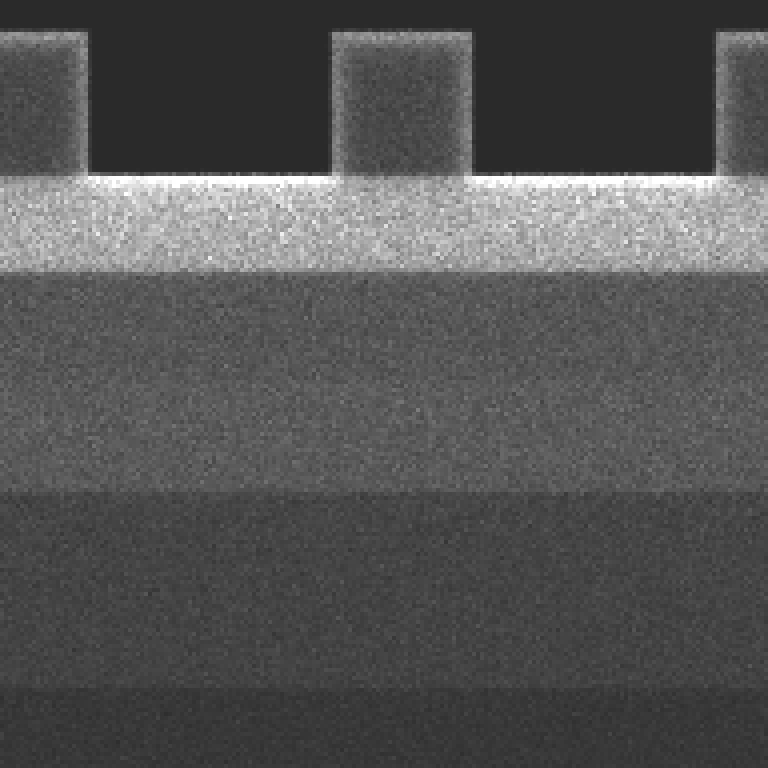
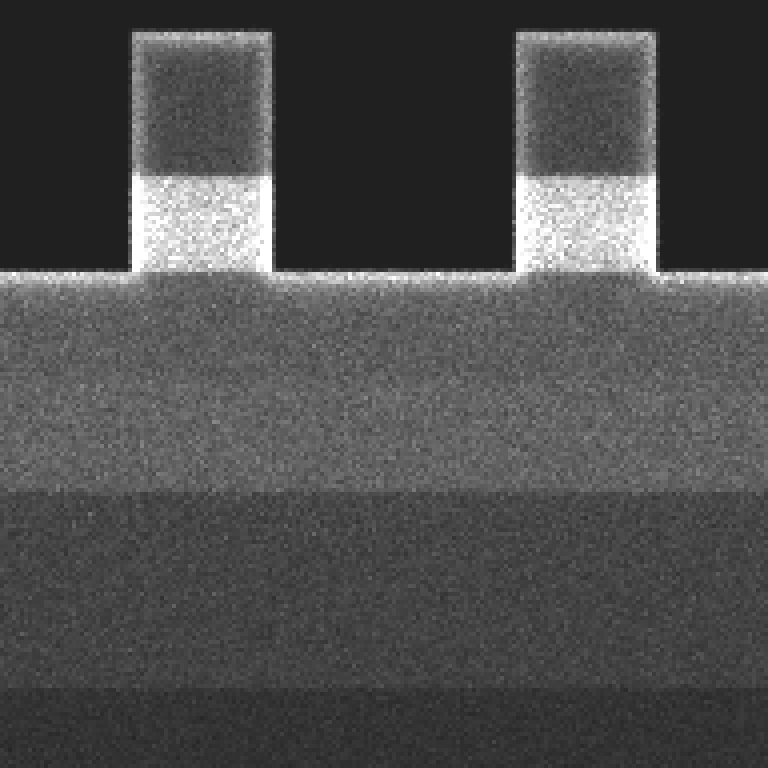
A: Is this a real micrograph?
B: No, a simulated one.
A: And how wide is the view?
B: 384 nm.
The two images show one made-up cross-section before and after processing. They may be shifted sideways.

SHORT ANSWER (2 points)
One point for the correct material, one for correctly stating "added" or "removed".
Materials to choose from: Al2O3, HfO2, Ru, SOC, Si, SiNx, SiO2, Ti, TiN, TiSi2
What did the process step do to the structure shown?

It removed HfO2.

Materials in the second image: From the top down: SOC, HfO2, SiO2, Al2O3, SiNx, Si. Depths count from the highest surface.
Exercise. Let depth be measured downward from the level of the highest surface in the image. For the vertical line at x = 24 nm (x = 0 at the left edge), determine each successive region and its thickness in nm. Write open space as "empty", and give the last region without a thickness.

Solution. empty 120, SiO2 54, Al2O3 56, SiNx 98, Si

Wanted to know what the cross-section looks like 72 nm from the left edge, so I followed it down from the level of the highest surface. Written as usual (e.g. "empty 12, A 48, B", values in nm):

SOC 72, HfO2 48, SiO2 54, Al2O3 56, SiNx 98, Si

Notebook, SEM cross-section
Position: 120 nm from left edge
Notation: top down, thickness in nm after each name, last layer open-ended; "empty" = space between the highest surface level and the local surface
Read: SOC 72, HfO2 48, SiO2 54, Al2O3 56, SiNx 98, Si